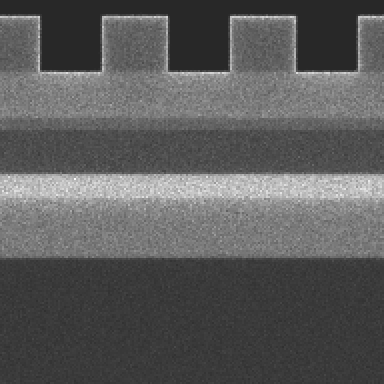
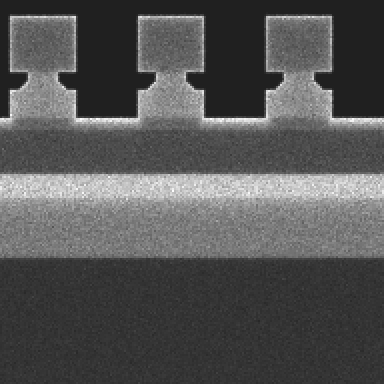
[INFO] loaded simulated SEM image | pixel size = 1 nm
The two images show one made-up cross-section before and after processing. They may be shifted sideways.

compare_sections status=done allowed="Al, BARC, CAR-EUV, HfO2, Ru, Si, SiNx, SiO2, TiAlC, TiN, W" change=removed material="Ru"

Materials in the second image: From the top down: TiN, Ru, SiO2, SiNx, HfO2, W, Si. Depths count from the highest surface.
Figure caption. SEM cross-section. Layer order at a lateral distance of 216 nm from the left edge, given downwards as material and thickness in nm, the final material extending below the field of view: empty 102, SiO2 12, SiNx 44, HfO2 24, W 60, Si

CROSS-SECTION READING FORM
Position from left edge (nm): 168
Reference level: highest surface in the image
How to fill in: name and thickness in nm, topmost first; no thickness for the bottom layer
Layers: TiN 56, Ru 46, SiO2 12, SiNx 44, HfO2 24, W 60, Si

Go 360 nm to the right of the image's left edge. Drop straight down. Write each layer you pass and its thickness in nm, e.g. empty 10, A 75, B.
empty 102, SiO2 12, SiNx 44, HfO2 24, W 60, Si